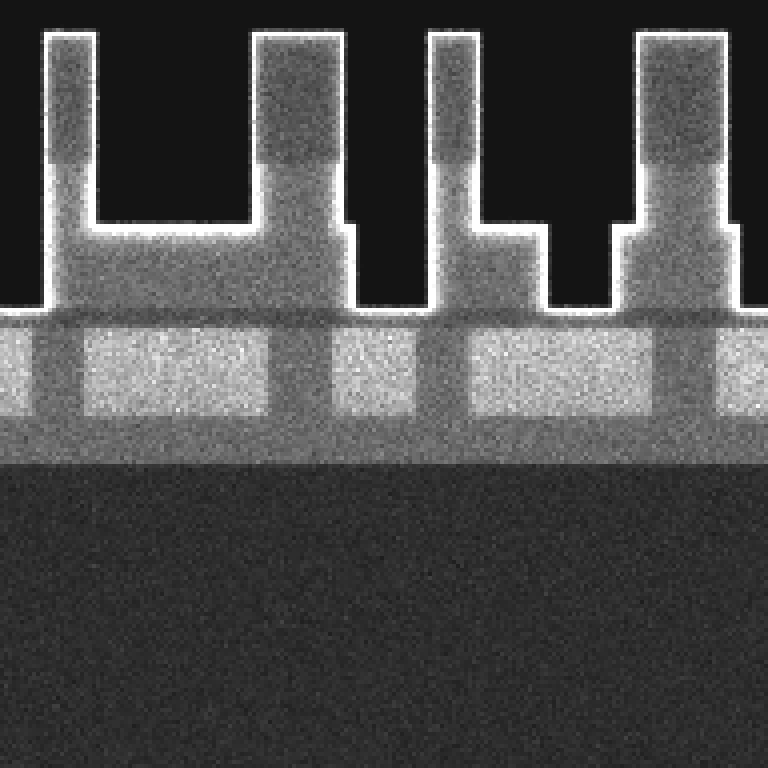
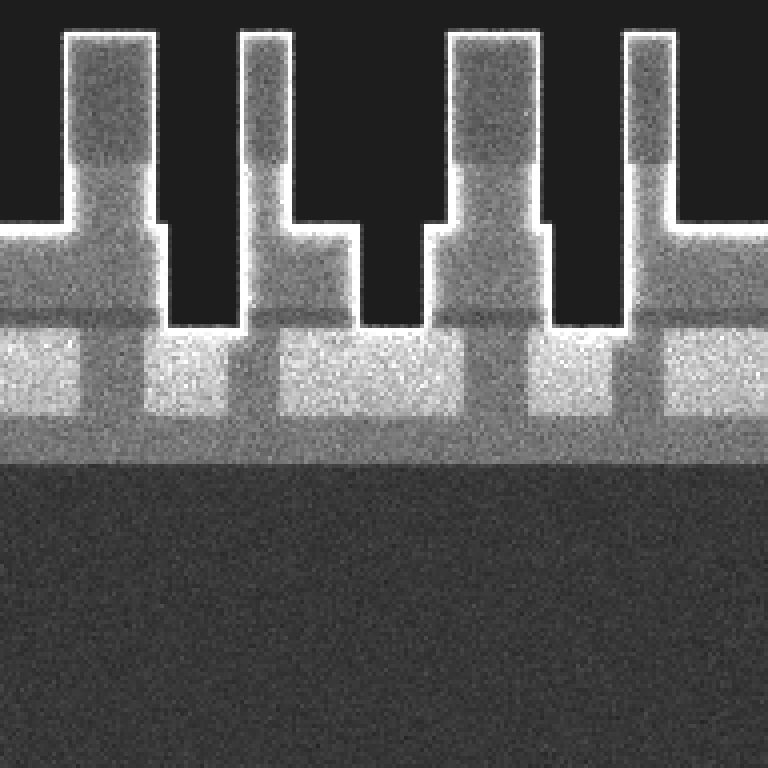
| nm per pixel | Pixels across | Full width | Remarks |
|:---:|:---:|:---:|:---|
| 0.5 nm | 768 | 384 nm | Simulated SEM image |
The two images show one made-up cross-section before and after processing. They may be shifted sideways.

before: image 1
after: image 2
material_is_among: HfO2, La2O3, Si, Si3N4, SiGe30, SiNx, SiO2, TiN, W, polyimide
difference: Si3N4, removed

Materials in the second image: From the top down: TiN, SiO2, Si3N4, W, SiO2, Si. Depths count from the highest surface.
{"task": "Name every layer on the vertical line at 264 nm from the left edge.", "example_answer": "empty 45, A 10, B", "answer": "TiN 66, SiO2 72, Si3N4 10, W 44, SiO2 24, Si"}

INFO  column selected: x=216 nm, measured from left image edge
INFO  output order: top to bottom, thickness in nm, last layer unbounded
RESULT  empty 96, SiO2 42, Si3N4 10, W 44, SiO2 24, Si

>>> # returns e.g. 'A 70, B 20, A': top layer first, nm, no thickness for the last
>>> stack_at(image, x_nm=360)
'empty 96, SiO2 42, Si3N4 10, W 44, SiO2 24, Si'